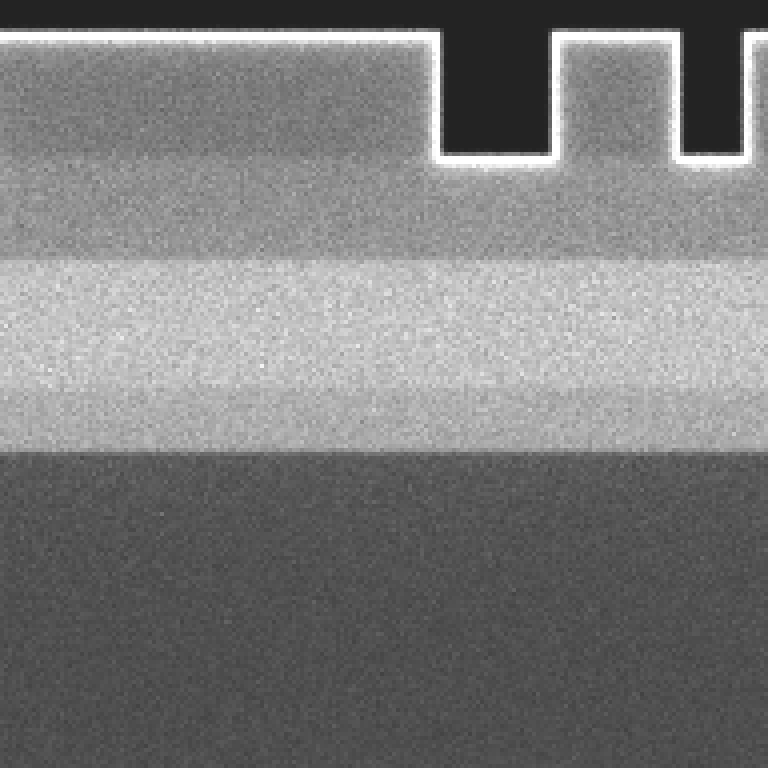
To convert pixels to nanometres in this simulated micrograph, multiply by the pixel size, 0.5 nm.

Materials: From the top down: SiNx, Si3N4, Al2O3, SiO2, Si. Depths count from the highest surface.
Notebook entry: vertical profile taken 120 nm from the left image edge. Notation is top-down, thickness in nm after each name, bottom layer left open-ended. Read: SiNx 62, Si3N4 52, Al2O3 64, SiO2 32, Si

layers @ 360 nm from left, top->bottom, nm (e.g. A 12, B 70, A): empty 62, Si3N4 52, Al2O3 64, SiO2 32, Si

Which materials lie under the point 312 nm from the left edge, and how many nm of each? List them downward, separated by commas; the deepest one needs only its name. SiNx 62, Si3N4 52, Al2O3 64, SiO2 32, Si